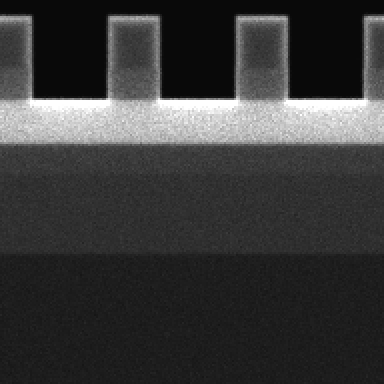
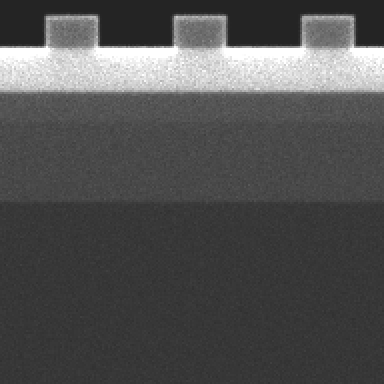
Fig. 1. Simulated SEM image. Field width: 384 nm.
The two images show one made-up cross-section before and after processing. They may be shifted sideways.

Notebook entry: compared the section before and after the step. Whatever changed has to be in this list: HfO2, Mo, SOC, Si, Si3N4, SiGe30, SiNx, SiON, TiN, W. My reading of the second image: SOC removed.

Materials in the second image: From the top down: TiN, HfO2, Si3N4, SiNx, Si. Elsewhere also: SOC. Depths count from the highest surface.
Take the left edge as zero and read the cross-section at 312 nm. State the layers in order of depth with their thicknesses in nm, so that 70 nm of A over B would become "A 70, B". TiN 32, HfO2 44, Si3N4 30, SiNx 80, Si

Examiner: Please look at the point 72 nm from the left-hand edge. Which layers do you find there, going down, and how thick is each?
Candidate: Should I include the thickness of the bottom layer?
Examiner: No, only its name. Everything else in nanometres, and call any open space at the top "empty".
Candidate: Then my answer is TiN 32, HfO2 44, Si3N4 30, SiNx 80, Si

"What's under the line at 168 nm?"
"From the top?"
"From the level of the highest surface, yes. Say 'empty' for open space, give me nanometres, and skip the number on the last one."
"empty 32, HfO2 44, Si3N4 30, SiNx 80, Si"